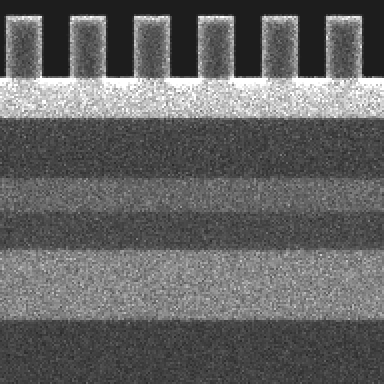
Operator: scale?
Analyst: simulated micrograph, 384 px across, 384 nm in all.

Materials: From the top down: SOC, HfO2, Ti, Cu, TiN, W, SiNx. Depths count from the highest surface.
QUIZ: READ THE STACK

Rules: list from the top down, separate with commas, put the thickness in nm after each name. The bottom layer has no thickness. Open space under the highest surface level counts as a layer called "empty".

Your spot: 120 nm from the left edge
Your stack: empty 62, HfO2 40, Ti 60, Cu 34, TiN 38, W 70, SiNx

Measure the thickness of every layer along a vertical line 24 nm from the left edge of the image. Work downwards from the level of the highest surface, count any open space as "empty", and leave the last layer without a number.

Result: SOC 62, HfO2 40, Ti 60, Cu 34, TiN 38, W 70, SiNx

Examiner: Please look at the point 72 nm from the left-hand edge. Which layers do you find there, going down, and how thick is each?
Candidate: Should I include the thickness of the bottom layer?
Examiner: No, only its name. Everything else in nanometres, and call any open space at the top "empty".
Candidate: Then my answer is SOC 62, HfO2 40, Ti 60, Cu 34, TiN 38, W 70, SiNx